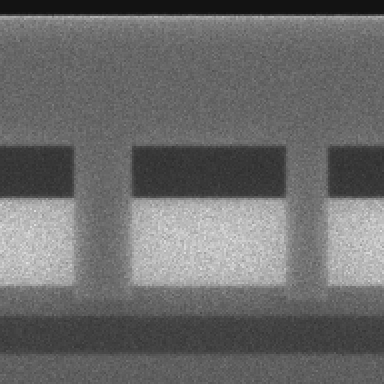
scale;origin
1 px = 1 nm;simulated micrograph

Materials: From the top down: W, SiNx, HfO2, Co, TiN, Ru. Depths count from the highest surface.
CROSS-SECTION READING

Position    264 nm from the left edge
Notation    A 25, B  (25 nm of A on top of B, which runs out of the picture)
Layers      W 130, SiNx 52, HfO2 88, Co 30, TiN 38, Ru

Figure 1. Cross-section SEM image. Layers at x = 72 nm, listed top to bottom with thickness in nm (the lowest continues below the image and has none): W 130, SiNx 52, HfO2 88, Co 30, TiN 38, Ru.